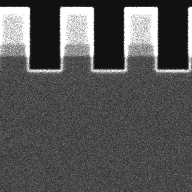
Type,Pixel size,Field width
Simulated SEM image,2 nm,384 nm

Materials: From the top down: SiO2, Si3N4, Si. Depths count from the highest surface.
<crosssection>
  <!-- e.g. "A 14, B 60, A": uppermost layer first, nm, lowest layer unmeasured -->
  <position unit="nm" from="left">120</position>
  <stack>empty 124, Si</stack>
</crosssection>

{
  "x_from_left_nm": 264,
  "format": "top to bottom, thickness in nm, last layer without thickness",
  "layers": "SiO2 72, Si3N4 24, Si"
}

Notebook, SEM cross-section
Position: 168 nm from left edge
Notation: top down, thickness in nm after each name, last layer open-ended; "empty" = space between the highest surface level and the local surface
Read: SiO2 72, Si3N4 24, Si